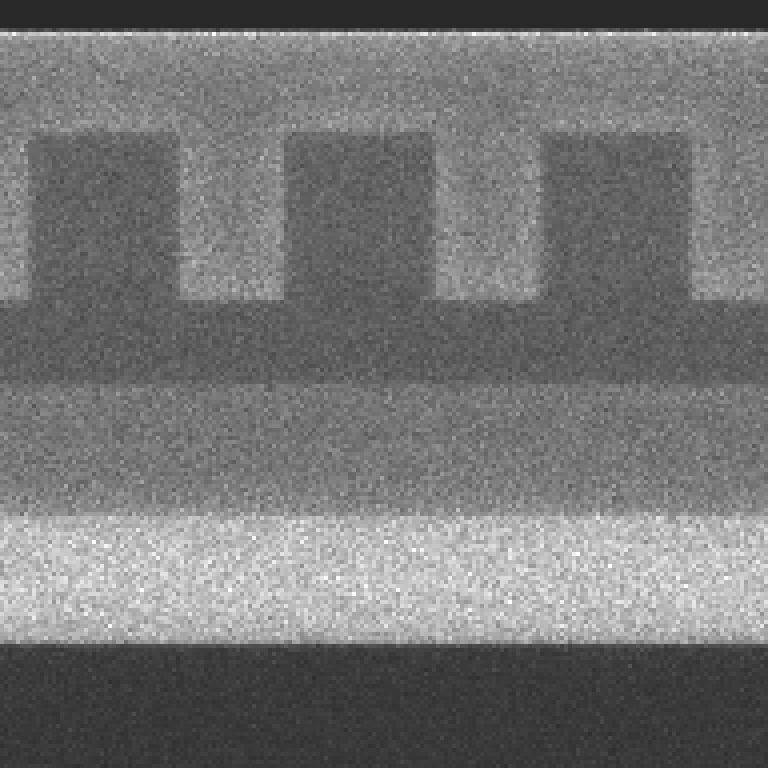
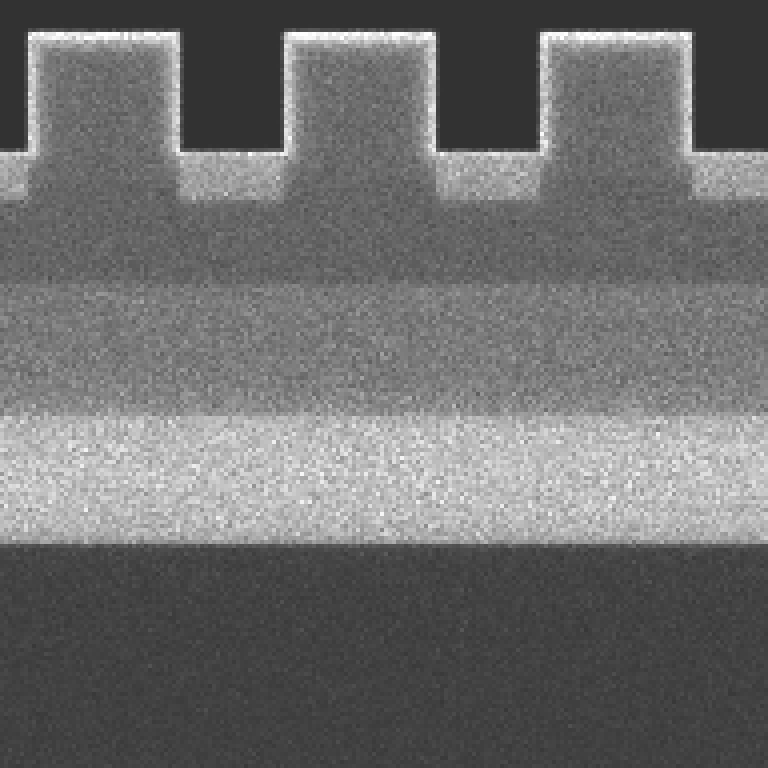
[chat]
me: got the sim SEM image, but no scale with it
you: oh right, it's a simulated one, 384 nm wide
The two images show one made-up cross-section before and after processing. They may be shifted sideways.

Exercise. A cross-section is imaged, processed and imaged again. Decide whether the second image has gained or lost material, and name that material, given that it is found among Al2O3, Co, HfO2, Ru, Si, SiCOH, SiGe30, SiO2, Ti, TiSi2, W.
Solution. removed: W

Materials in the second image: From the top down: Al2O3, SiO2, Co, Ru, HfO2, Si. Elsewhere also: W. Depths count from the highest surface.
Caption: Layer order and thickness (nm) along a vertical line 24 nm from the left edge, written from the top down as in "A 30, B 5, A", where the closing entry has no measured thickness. Al2O3 74, SiO2 52, Co 28, Ru 38, HfO2 64, Si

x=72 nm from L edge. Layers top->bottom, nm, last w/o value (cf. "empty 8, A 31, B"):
Al2O3 74, SiO2 52, Co 28, Ru 38, HfO2 64, Si